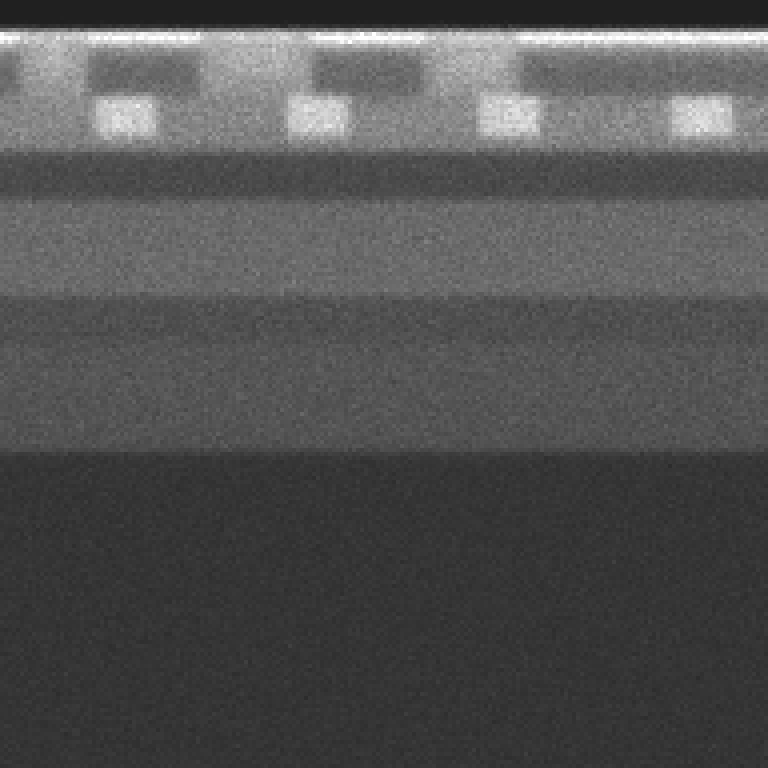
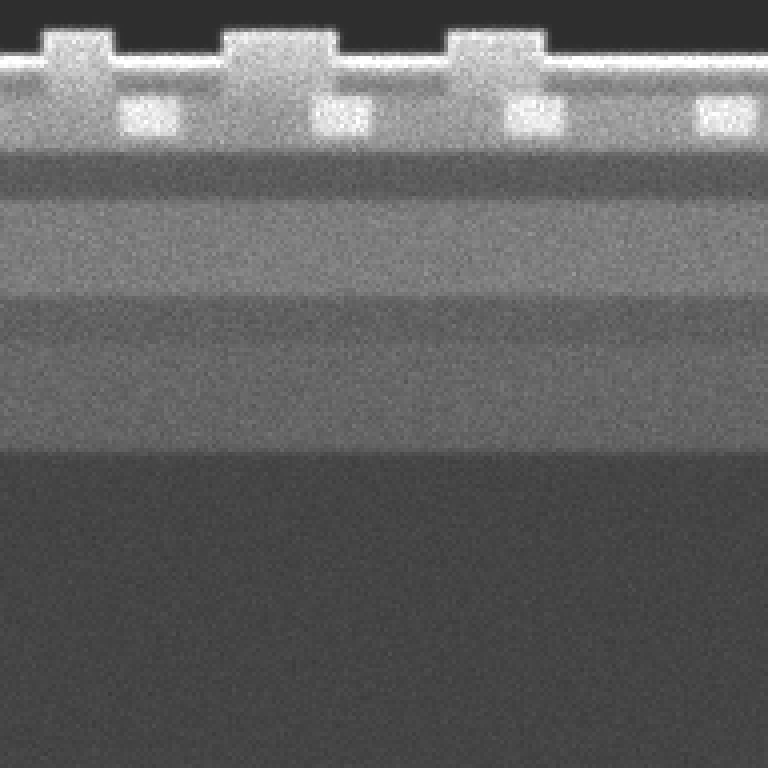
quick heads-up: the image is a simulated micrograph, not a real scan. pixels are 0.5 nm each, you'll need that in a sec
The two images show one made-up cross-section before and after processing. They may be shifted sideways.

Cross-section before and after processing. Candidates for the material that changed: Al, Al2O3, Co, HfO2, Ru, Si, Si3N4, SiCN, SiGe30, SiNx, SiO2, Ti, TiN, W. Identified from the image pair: SiO2 (removed).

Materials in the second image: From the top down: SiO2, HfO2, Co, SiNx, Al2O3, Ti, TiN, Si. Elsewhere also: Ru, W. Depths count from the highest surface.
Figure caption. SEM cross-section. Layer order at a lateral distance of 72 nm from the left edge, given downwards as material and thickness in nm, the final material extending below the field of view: empty 12, SiO2 20, HfO2 20, Co 8, SiNx 24, Al2O3 48, Ti 24, TiN 54, Si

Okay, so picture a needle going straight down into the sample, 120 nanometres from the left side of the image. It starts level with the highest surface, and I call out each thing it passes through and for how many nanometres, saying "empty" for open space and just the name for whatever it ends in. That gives Ru 32, Co 28, SiNx 24, Al2O3 48, Ti 24, TiN 54, Si